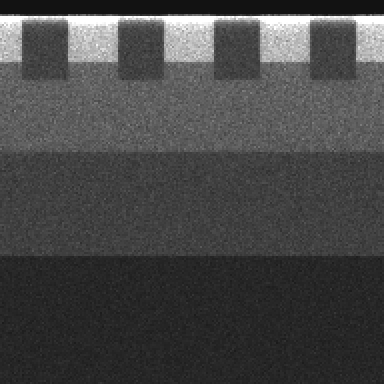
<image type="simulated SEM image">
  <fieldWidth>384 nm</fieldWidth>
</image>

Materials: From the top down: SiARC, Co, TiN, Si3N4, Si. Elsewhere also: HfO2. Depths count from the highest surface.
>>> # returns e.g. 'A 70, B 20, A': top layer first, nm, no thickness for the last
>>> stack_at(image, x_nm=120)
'SiARC 64, Co 72, TiN 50, Si3N4 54, Si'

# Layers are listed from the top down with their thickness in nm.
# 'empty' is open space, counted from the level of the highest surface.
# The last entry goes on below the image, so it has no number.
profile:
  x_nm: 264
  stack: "HfO2 46, Co 90, TiN 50, Si3N4 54, Si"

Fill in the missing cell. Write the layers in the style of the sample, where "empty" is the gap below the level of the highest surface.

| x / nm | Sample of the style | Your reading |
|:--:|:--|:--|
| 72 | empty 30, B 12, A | HfO2 46, Co 90, TiN 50, Si3N4 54, Si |